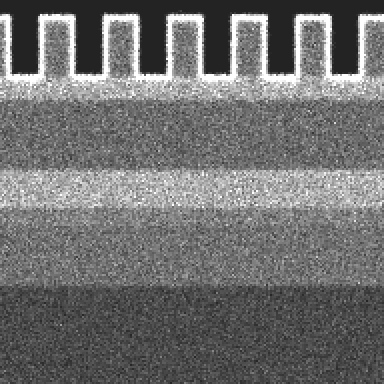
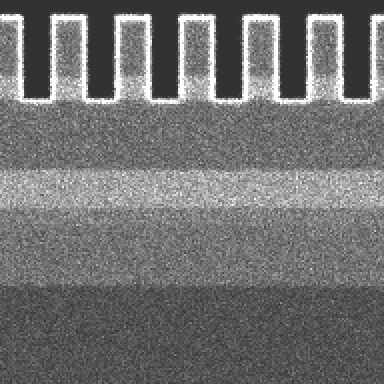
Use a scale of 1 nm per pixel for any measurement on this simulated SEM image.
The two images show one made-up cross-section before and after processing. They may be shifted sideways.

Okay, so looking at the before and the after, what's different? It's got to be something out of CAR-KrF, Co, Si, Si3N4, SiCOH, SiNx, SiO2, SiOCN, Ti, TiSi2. Co, removed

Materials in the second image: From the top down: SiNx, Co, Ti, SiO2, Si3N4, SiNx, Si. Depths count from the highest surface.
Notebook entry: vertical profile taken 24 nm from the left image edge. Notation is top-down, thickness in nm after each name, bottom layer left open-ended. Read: empty 84, Ti 70, SiO2 38, Si3N4 18, SiNx 60, Si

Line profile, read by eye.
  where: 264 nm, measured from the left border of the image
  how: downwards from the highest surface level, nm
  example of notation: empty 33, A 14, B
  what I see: SiNx 60, Co 24, Ti 70, SiO2 38, Si3N4 18, SiNx 60, Si